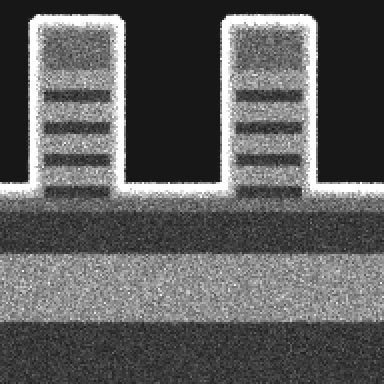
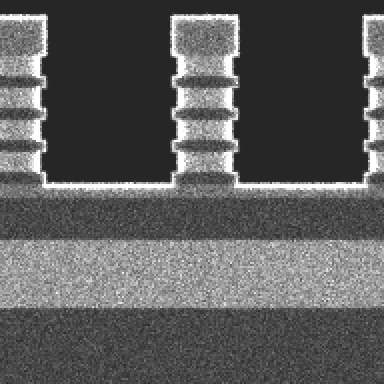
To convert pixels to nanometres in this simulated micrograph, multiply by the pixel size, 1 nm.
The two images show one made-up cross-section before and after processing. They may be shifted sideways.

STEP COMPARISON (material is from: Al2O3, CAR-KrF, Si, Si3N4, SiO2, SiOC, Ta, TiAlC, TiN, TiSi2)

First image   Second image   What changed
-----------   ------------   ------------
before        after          Al2O3, removed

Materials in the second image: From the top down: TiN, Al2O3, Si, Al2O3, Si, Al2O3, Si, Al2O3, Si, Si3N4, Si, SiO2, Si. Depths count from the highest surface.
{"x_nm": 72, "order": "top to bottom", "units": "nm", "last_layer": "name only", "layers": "empty 168, Si3N4 14, Si 42, SiO2 68, Si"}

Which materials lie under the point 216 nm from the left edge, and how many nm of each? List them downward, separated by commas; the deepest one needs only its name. TiN 40, Al2O3 20, Si 12, Al2O3 20, Si 12, Al2O3 20, Si 12, Al2O3 20, Si 12, Si3N4 14, Si 42, SiO2 68, Si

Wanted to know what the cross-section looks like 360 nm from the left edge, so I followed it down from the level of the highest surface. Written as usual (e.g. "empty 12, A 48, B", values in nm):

empty 168, Si3N4 14, Si 42, SiO2 68, Si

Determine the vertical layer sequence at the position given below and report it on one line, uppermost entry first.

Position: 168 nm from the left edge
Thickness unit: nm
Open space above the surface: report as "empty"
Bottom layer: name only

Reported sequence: empty 168, Si3N4 14, Si 42, SiO2 68, Si